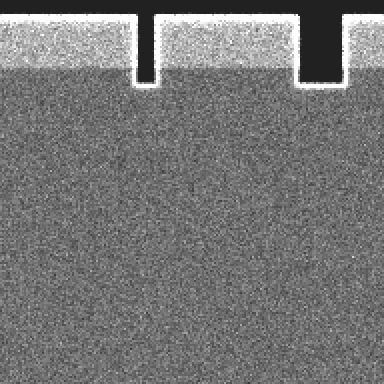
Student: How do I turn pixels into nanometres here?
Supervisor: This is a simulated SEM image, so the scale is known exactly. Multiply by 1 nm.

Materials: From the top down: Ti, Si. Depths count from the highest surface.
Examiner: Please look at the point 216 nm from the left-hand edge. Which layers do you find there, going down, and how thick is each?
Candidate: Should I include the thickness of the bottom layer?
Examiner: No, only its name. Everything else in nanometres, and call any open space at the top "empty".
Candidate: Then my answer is Ti 52, Si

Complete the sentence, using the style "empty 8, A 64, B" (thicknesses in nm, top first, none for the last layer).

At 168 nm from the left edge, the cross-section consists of Ti 52, Si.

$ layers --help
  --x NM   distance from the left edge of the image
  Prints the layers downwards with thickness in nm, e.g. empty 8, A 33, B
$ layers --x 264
Ti 52, Si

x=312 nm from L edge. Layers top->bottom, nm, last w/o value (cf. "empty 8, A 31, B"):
empty 68, Si